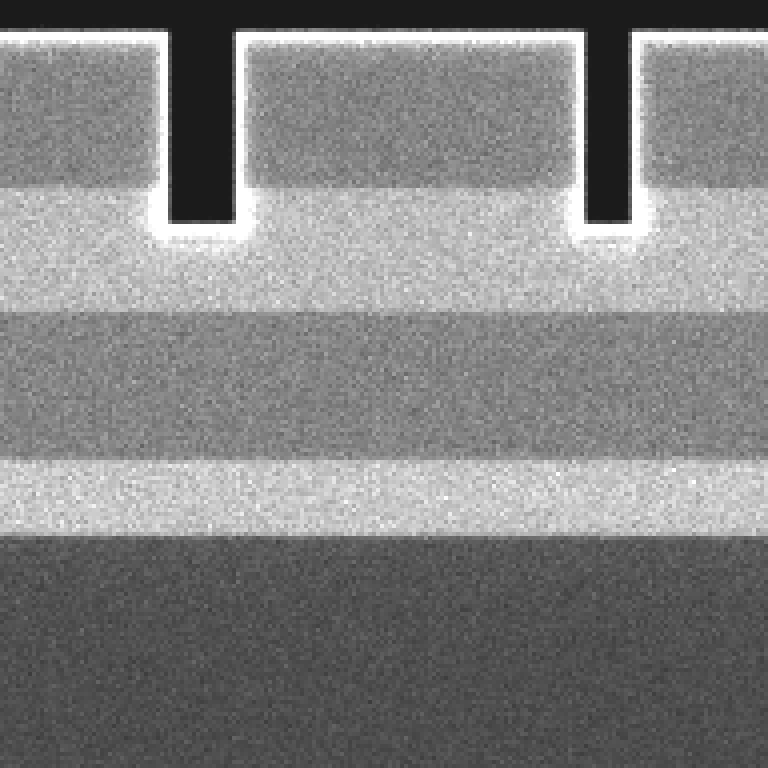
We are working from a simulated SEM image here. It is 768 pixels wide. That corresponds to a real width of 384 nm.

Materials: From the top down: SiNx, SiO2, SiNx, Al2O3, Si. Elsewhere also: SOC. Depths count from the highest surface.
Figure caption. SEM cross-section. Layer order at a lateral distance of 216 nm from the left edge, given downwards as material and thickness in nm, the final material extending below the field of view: SiNx 78, SiO2 62, SiNx 74, Al2O3 38, Si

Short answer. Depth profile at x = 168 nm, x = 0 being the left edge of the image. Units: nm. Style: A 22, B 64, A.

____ SiNx 78, SiO2 62, SiNx 74, Al2O3 38, Si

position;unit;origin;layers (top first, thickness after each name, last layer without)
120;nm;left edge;SiNx 78, SiO2 62, SiNx 74, Al2O3 38, Si